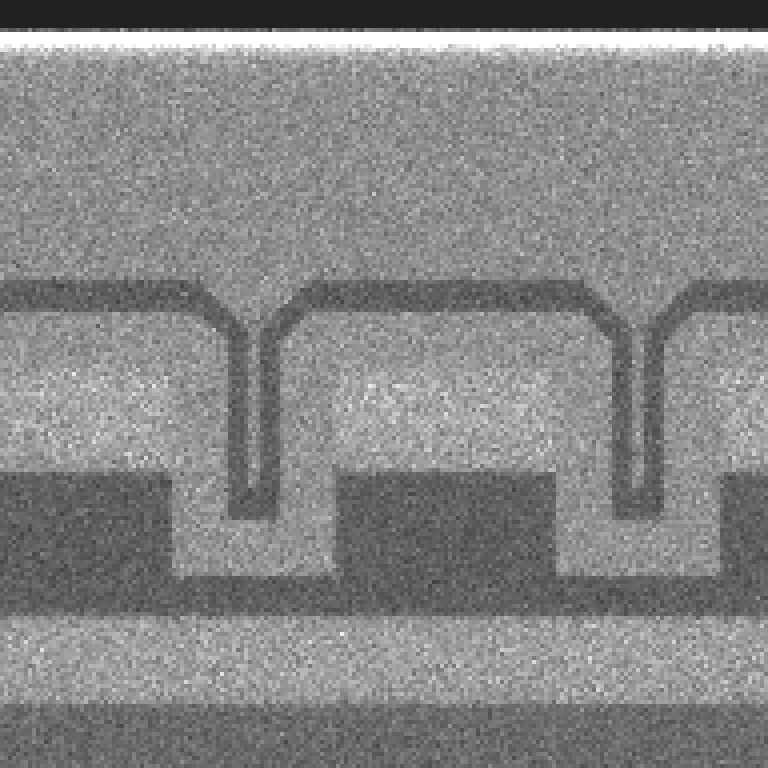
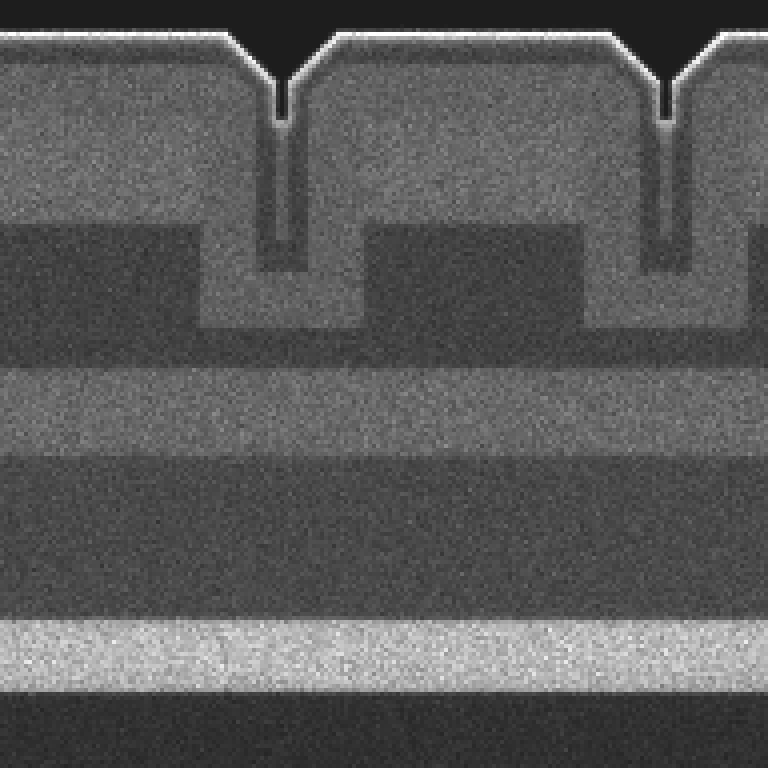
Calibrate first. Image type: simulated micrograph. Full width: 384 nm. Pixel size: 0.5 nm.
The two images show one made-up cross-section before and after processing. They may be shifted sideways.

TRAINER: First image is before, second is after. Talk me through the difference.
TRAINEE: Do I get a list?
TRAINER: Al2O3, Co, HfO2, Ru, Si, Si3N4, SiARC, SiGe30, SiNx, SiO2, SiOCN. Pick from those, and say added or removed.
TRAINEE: removed: SiO2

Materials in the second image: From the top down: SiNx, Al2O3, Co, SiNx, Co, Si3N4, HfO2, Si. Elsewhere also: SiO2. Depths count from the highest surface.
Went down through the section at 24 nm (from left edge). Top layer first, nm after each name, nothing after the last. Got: SiNx 16, Al2O3 28, Co 52, SiNx 72, Co 44, Si3N4 82, HfO2 36, Si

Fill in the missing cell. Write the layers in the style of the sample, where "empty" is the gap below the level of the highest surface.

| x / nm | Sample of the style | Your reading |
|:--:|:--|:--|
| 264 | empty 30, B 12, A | SiNx 16, Al2O3 28, Co 52, SiNx 72, Co 44, Si3N4 82, HfO2 36, Si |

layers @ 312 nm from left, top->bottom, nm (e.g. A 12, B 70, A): empty 8, SiNx 16, Al2O3 124, SiNx 20, Co 44, Si3N4 82, HfO2 36, Si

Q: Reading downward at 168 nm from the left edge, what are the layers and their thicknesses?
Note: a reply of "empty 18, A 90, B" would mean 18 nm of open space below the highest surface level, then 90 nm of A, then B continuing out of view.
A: SiNx 16, Al2O3 132, SiNx 20, Co 44, Si3N4 82, HfO2 36, Si